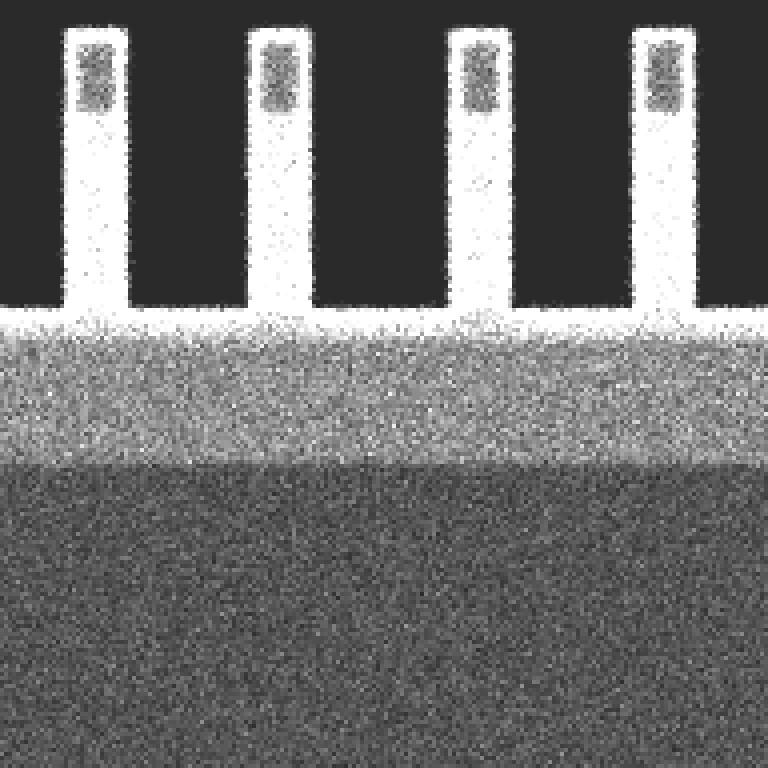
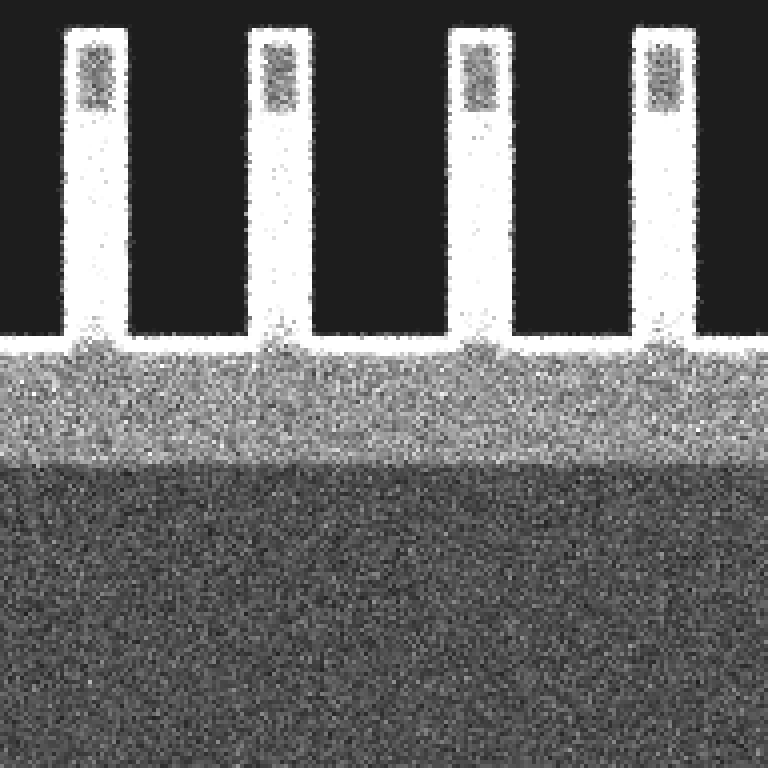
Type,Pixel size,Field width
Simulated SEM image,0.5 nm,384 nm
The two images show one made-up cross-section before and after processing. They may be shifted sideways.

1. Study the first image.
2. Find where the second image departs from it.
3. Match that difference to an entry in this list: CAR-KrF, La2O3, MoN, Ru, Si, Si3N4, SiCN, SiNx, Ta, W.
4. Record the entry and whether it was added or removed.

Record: Ru / removed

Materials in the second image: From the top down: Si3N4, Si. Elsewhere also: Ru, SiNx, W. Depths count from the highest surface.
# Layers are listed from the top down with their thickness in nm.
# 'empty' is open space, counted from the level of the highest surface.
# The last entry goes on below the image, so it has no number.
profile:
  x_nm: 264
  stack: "empty 154, Si3N4 62, Si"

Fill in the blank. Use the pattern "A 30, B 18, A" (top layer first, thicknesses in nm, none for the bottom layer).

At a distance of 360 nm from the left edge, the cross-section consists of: empty 154, Si3N4 62, Si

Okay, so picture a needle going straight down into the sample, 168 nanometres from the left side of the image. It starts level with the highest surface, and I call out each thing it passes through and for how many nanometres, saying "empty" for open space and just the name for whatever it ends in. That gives empty 154, Si3N4 62, Si